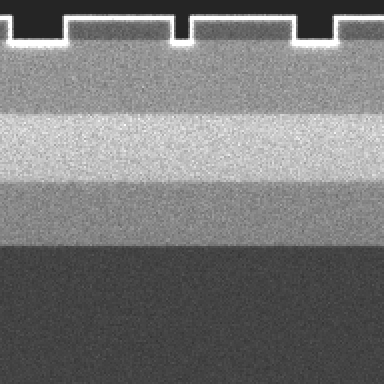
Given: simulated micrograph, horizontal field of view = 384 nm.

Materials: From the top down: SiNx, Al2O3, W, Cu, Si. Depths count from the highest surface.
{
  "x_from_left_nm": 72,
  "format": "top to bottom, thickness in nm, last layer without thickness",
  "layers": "SiNx 24, Al2O3 74, W 68, Cu 64, Si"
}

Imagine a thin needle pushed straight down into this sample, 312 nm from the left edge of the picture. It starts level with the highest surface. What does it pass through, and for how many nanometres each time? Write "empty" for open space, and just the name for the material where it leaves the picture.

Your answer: empty 24, Al2O3 74, W 68, Cu 64, Si